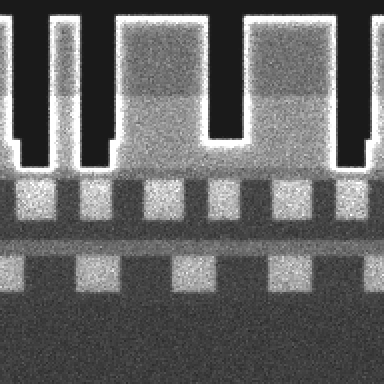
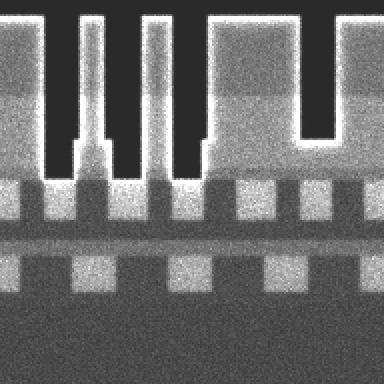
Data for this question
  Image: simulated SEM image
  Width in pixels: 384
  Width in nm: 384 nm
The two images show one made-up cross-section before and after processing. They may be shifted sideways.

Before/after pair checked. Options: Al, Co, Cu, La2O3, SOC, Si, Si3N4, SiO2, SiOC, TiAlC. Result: removed Si3N4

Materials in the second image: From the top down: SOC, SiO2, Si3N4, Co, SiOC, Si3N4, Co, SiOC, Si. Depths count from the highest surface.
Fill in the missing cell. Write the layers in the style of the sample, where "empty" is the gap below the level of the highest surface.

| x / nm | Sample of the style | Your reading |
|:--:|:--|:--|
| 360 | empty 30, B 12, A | SOC 80, SiO2 72, Si3N4 12, SiOC 60, Si3N4 16, Co 36, SiOC 12, Si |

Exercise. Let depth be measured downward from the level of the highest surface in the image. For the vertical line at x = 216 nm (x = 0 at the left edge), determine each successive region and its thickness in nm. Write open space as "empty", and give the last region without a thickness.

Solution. SOC 80, SiO2 72, Si3N4 12, SiOC 60, Si3N4 16, SiOC 48, Si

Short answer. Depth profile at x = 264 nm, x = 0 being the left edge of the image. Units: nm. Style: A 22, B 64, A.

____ SOC 80, SiO2 72, Si3N4 12, Co 40, SiOC 20, Si3N4 16, Co 36, SiOC 12, Si